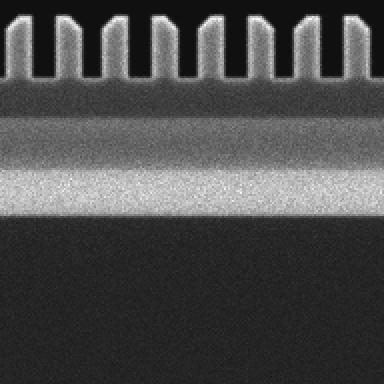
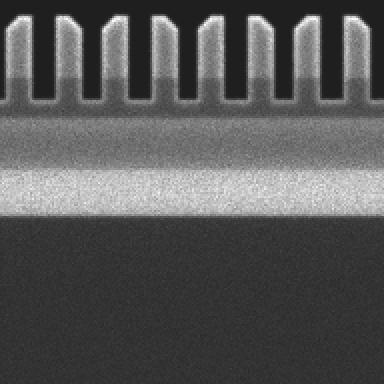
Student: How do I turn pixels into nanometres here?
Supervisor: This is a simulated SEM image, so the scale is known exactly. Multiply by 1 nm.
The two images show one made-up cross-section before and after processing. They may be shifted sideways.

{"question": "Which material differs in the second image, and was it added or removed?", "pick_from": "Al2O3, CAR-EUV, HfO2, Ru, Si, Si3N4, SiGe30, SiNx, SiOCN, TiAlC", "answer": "SiNx, removed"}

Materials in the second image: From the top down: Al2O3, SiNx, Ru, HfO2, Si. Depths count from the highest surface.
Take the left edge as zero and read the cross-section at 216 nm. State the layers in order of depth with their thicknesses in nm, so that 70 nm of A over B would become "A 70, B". Al2O3 62, SiNx 40, Ru 52, HfO2 46, Si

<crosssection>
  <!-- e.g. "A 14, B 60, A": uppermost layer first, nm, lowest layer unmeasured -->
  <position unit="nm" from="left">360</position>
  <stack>empty 4, Al2O3 58, SiNx 40, Ru 52, HfO2 46, Si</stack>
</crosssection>